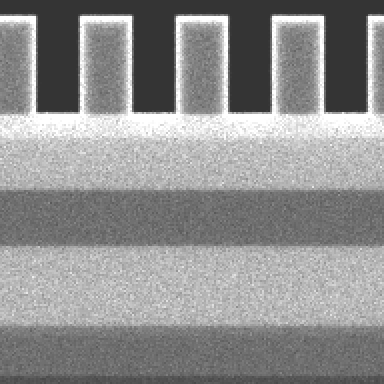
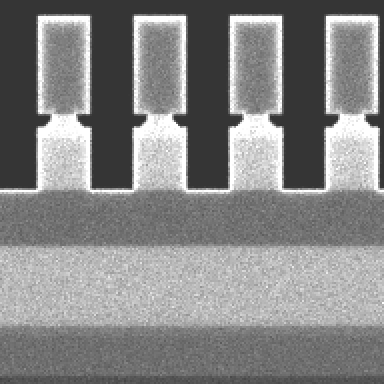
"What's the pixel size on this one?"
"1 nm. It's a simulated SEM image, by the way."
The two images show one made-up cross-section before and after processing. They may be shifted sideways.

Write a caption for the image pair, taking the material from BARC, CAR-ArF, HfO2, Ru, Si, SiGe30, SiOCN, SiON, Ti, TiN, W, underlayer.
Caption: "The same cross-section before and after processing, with Ru and W removed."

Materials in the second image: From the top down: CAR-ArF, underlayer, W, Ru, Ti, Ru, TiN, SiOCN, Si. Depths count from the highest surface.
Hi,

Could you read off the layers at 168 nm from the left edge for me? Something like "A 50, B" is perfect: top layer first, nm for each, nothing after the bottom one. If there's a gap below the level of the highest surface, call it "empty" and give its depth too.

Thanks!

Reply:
CAR-ArF 62, underlayer 36, W 24, Ru 52, Ti 56, Ru 80, TiN 10, SiOCN 40, Si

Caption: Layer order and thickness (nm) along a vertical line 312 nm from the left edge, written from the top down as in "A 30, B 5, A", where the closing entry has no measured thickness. empty 174, Ti 56, Ru 80, TiN 10, SiOCN 40, Si